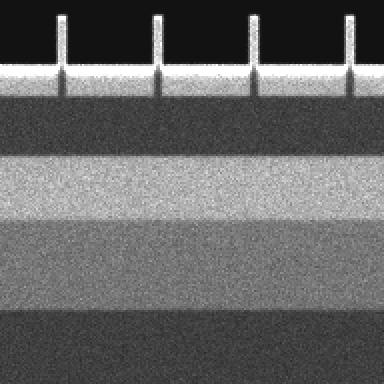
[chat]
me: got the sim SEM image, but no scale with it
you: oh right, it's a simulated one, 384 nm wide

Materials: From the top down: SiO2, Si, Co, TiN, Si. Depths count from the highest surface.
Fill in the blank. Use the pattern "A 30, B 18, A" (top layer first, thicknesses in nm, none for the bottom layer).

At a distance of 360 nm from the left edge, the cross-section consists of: empty 50, SiO2 30, Si 60, Co 64, TiN 90, Si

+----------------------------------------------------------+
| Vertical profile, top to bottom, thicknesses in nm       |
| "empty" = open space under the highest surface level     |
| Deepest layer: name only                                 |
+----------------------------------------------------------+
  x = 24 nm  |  empty 50, SiO2 30, Si 60, Co 64, TiN 90, Si